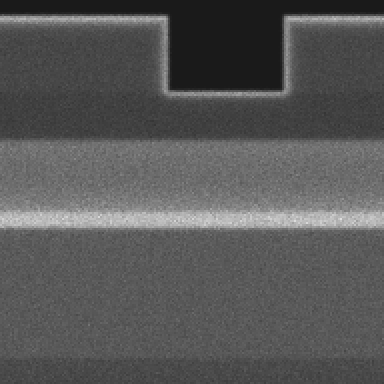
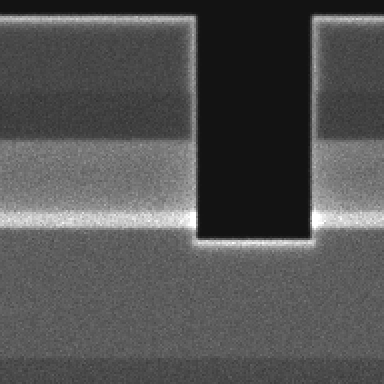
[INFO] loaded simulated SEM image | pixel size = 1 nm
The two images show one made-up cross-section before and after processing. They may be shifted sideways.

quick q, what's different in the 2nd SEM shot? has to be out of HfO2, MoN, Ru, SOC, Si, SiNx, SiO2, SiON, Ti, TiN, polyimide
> HfO2 and Ru and SiNx and TiN removed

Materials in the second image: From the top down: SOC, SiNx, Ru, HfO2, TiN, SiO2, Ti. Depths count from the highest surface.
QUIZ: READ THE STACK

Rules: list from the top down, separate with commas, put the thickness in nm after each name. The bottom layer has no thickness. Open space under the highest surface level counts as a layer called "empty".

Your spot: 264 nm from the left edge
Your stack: empty 224, SiO2 118, Ti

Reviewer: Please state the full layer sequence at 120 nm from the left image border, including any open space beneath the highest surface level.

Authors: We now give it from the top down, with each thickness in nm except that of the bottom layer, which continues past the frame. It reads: SOC 76, SiNx 48, Ru 72, HfO2 16, TiN 12, SiO2 118, Ti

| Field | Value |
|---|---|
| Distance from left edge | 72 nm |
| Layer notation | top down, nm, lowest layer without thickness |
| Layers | SOC 76, SiNx 48, Ru 72, HfO2 16, TiN 12, SiO2 118, Ti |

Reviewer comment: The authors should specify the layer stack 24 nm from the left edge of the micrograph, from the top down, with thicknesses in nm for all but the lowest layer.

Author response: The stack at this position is SOC 76, SiNx 48, Ru 72, HfO2 16, TiN 12, SiO2 118, Ti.